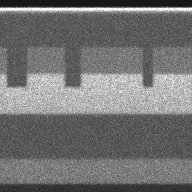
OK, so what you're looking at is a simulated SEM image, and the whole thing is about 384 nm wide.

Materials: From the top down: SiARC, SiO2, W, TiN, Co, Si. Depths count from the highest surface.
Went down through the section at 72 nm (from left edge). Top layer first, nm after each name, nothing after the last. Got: SiARC 78, SiO2 54, W 80, TiN 90, Co 50, Si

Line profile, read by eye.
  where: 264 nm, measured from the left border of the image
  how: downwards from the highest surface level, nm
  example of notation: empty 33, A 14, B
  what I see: SiARC 78, SiO2 54, W 80, TiN 90, Co 50, Si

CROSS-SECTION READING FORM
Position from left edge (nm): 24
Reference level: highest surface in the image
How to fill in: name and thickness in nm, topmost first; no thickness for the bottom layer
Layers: SiARC 158, W 54, TiN 90, Co 50, Si